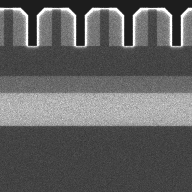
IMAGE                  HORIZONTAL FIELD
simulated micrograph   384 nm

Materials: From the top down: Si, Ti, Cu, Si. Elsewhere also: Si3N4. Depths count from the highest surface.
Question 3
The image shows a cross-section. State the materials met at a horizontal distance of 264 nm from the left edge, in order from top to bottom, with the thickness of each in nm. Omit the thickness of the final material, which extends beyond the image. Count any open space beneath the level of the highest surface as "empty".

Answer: empty 76, Si 60, Ti 34, Cu 66, Si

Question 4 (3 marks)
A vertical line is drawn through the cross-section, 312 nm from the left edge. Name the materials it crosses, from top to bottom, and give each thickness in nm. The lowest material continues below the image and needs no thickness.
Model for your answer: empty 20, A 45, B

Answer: Si 136, Ti 34, Cu 66, Si